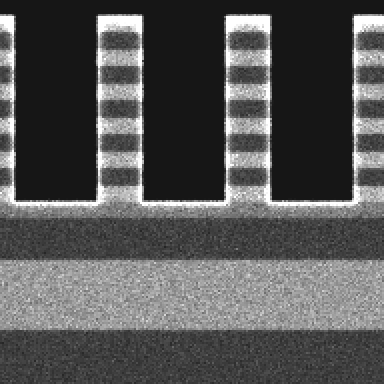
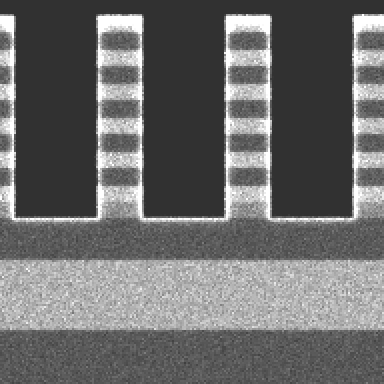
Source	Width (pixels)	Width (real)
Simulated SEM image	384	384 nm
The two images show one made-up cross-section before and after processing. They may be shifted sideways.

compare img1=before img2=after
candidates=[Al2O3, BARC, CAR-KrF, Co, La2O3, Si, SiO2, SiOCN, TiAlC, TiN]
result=removed:TiN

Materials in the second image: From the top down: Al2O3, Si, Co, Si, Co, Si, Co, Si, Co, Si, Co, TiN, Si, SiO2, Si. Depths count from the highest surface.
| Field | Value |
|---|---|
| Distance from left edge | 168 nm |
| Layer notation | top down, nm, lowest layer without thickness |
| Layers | empty 202, Si 42, SiO2 70, Si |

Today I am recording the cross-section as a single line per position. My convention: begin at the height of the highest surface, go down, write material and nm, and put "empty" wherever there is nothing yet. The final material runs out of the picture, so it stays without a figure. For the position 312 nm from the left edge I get empty 202, Si 42, SiO2 70, Si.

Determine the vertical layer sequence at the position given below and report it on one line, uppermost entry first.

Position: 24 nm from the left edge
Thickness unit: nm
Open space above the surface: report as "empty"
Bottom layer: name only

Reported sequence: empty 202, Si 42, SiO2 70, Si